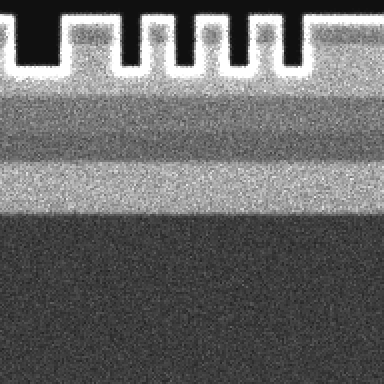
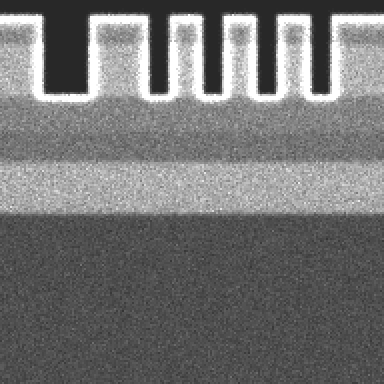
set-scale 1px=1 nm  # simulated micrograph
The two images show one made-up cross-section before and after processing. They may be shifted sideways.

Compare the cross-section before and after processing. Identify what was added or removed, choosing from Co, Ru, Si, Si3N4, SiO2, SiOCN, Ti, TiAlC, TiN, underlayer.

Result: SiO2 removed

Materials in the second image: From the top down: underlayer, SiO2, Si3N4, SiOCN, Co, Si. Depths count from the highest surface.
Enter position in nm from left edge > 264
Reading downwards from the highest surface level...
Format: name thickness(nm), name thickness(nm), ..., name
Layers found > empty 80, Si3N4 36, SiOCN 30, Co 52, Si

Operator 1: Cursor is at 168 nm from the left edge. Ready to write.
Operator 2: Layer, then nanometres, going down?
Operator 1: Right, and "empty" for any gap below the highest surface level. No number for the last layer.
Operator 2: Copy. empty 80, Si3N4 36, SiOCN 30, Co 52, Si